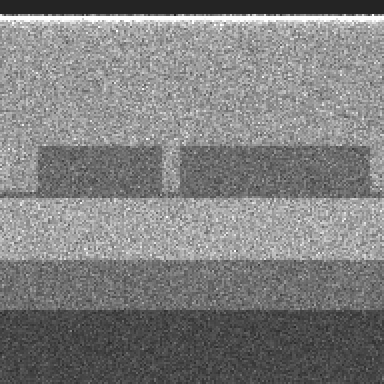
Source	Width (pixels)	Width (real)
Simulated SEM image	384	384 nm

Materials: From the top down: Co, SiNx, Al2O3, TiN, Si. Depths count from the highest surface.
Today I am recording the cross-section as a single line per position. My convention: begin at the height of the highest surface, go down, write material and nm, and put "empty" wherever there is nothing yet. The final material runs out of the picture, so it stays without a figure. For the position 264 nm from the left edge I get Co 130, SiNx 52, Al2O3 62, TiN 50, Si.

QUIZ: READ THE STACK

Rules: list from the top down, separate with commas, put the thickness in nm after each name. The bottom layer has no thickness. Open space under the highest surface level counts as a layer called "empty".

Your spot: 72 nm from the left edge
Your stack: Co 130, SiNx 52, Al2O3 62, TiN 50, Si